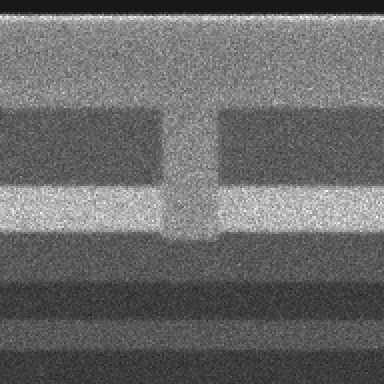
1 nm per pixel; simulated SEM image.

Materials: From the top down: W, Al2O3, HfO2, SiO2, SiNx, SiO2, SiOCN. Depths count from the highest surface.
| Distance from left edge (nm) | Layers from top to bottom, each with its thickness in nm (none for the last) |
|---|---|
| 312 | W 92, Al2O3 78, HfO2 46, SiO2 50, SiNx 38, SiO2 30, SiOCN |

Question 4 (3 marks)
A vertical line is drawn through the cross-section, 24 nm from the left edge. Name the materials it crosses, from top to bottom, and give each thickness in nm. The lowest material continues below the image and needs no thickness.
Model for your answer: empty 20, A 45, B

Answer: W 92, Al2O3 78, HfO2 46, SiO2 50, SiNx 38, SiO2 30, SiOCN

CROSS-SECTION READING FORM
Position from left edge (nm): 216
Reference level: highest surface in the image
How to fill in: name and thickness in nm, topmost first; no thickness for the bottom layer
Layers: W 224, SiO2 42, SiNx 38, SiO2 30, SiOCN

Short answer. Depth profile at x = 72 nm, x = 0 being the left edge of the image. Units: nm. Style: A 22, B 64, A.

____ W 92, Al2O3 78, HfO2 46, SiO2 50, SiNx 38, SiO2 30, SiOCN